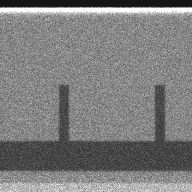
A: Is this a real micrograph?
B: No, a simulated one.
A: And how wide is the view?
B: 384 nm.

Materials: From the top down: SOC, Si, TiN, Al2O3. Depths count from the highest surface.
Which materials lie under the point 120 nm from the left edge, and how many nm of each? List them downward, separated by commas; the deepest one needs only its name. SOC 154, Si 172, TiN 24, Al2O3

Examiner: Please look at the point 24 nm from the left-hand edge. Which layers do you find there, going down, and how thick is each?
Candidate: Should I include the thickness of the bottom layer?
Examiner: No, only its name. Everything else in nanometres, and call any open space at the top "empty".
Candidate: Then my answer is SOC 266, Si 60, TiN 24, Al2O3